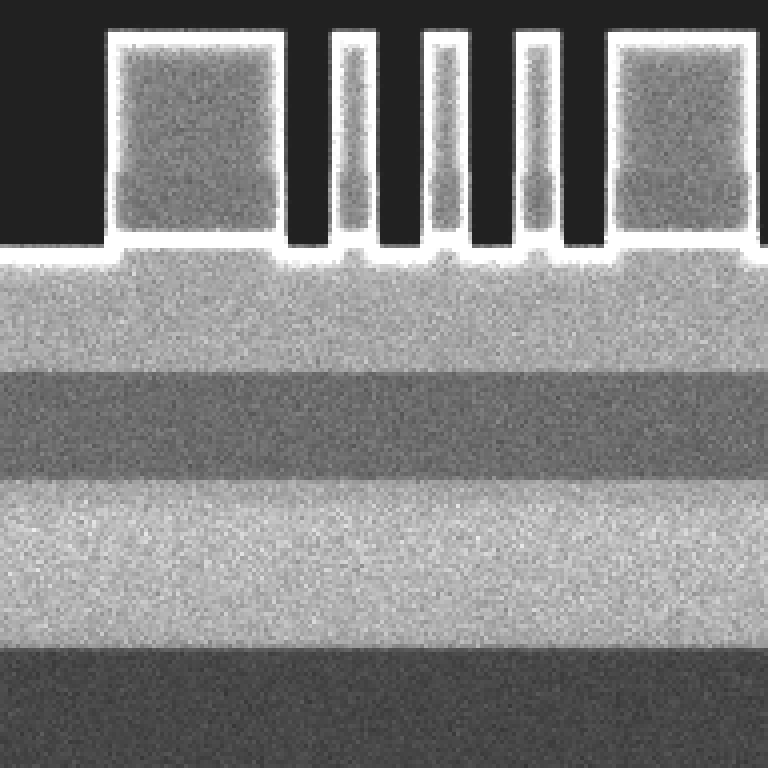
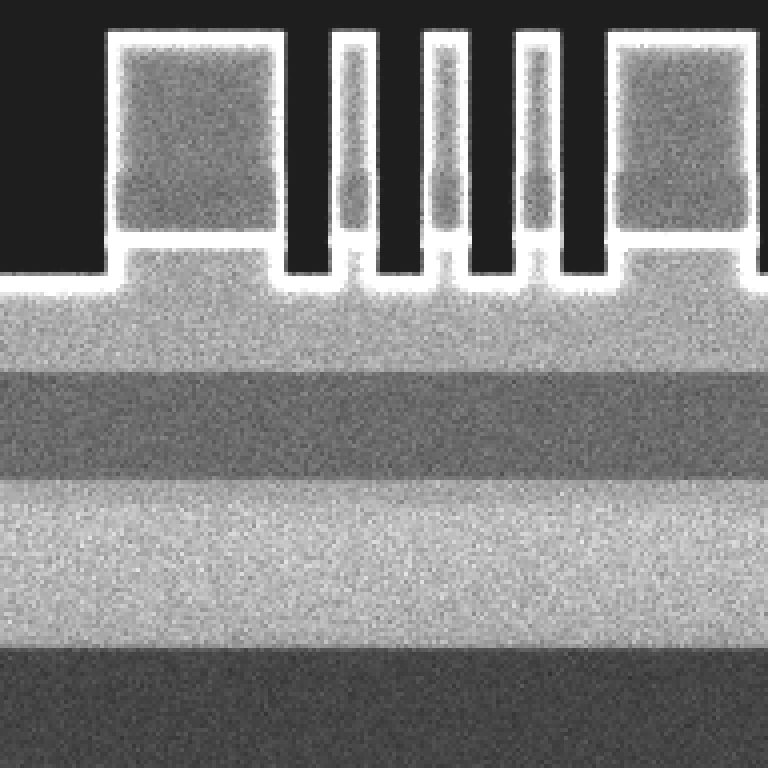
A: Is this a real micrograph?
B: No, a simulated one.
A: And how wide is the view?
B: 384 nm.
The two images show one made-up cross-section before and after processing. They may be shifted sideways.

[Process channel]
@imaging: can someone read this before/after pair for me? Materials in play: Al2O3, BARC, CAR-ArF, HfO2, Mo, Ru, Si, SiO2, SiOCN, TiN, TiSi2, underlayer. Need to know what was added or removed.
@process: SiO2 removed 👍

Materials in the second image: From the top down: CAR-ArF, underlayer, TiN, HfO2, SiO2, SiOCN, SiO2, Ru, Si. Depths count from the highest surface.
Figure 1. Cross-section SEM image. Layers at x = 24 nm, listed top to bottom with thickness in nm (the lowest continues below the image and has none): empty 122, SiO2 48, SiOCN 54, SiO2 12, Ru 72, Si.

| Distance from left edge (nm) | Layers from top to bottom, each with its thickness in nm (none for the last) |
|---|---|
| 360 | CAR-ArF 32, underlayer 38, TiN 30, HfO2 8, SiO2 62, SiOCN 54, SiO2 12, Ru 72, Si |